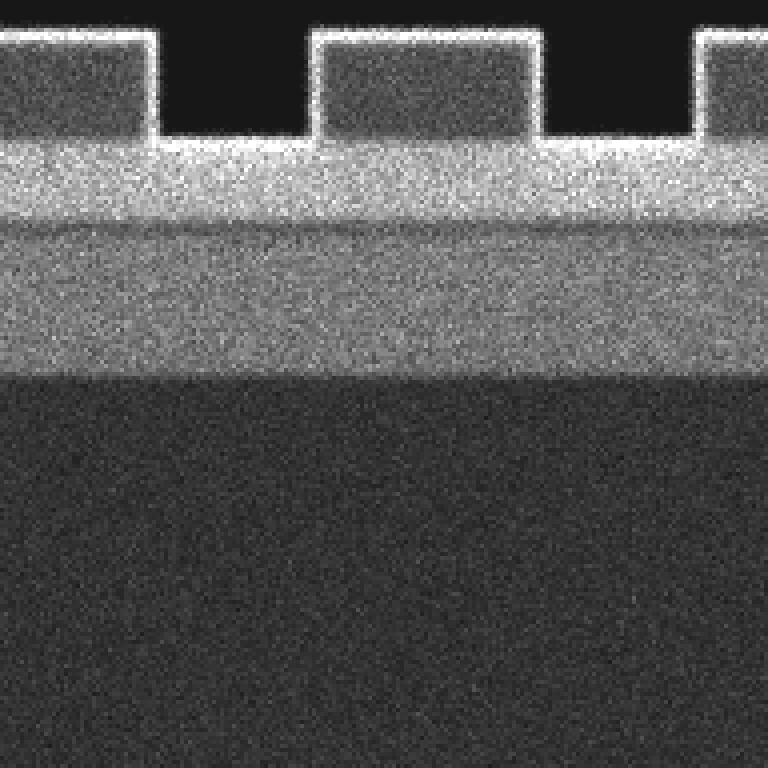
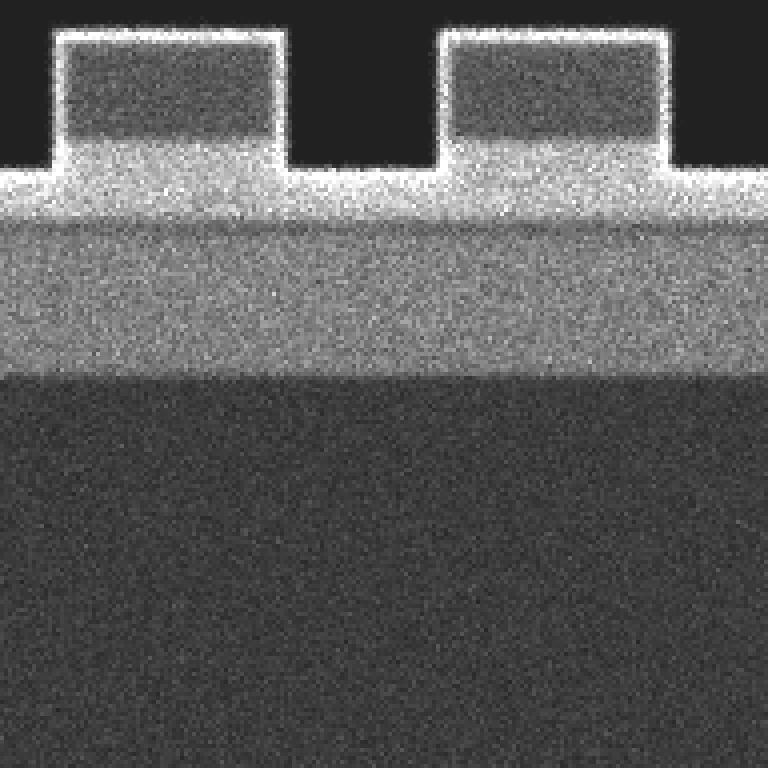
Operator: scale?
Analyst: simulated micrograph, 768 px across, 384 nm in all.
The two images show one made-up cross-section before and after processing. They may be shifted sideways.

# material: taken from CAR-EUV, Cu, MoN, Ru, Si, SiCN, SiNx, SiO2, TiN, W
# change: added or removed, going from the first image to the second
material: W
change: removed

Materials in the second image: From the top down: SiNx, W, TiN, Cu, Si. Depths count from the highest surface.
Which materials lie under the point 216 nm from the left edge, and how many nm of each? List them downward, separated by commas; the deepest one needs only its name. empty 70, W 24, TiN 8, Cu 70, Si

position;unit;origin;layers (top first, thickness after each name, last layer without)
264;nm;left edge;SiNx 54, W 40, TiN 8, Cu 70, Si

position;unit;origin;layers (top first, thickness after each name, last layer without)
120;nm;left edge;SiNx 54, W 40, TiN 8, Cu 70, Si